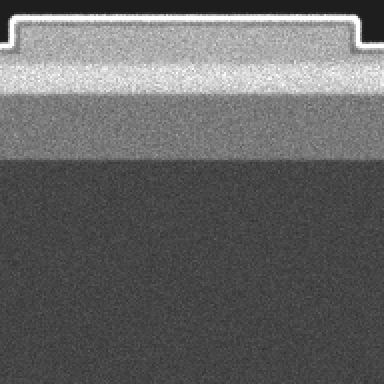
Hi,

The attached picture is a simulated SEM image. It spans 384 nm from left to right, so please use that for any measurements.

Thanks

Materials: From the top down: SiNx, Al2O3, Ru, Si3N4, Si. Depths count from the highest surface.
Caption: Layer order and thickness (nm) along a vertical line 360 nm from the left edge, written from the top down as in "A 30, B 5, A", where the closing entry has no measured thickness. empty 28, SiNx 10, Al2O3 10, Ru 30, Si3N4 66, Si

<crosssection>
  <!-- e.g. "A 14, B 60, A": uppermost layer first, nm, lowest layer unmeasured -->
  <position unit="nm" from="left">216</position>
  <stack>SiNx 10, Al2O3 38, Ru 30, Si3N4 66, Si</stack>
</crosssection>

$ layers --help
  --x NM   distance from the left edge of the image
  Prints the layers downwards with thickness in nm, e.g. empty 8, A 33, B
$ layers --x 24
SiNx 10, Al2O3 38, Ru 30, Si3N4 66, Si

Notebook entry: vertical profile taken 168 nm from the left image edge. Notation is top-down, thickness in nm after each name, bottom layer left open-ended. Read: SiNx 10, Al2O3 38, Ru 30, Si3N4 66, Si